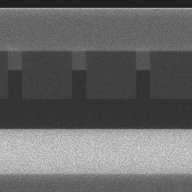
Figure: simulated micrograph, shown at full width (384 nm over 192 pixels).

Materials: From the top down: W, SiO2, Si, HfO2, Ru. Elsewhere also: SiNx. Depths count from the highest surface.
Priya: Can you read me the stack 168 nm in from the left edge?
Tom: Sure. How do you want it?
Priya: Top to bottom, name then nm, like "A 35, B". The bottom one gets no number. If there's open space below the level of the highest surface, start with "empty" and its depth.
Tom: W 86, SiO2 38, Si 118, HfO2 90, Ru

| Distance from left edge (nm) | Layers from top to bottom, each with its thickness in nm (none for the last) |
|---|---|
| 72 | W 86, SiNx 96, Si 60, HfO2 90, Ru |